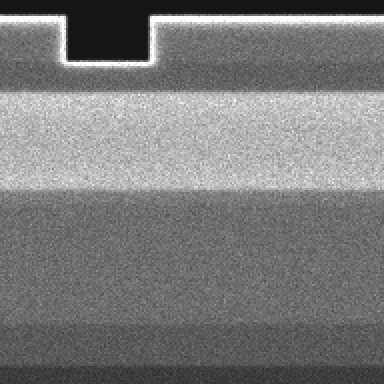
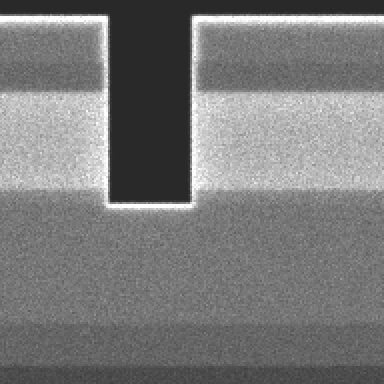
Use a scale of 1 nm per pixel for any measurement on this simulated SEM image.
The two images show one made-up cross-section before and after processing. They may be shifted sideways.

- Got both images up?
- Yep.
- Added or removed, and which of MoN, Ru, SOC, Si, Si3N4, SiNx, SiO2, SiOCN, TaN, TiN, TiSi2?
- removed, Ru and SiNx and TiN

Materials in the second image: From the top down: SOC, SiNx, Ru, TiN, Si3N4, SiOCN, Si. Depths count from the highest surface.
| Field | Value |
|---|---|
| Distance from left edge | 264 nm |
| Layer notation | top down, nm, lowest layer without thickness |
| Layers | SOC 46, SiNx 30, Ru 98, TiN 14, Si3N4 120, SiOCN 42, Si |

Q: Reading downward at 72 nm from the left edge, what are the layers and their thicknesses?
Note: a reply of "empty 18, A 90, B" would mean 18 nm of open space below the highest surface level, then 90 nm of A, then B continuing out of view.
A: SOC 46, SiNx 30, Ru 98, TiN 14, Si3N4 120, SiOCN 42, Si